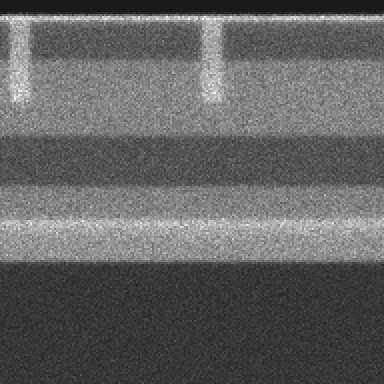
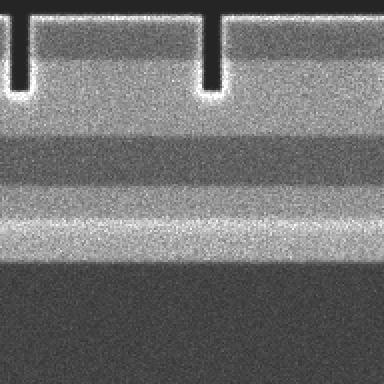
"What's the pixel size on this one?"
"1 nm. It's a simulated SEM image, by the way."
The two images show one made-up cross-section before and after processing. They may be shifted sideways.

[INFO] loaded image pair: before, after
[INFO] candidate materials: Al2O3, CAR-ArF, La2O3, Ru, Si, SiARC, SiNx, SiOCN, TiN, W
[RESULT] removed Ru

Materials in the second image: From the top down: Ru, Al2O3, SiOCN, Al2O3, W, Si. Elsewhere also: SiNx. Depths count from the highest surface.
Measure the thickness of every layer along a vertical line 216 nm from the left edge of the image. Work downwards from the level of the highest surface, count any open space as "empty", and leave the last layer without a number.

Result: empty 76, Ru 10, Al2O3 34, SiOCN 50, Al2O3 34, W 42, Si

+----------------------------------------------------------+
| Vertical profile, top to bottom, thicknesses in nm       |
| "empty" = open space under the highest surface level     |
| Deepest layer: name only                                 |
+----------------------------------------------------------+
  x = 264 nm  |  SiNx 44, Al2O3 76, SiOCN 50, Al2O3 34, W 42, Si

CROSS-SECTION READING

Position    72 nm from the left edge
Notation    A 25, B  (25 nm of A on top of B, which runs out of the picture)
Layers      SiNx 44, Al2O3 76, SiOCN 50, Al2O3 34, W 42, Si